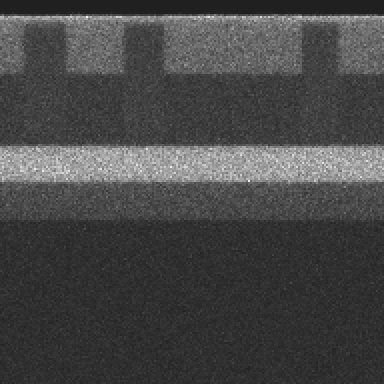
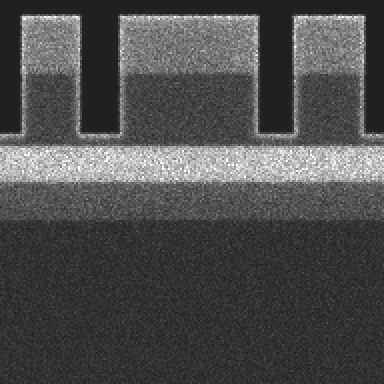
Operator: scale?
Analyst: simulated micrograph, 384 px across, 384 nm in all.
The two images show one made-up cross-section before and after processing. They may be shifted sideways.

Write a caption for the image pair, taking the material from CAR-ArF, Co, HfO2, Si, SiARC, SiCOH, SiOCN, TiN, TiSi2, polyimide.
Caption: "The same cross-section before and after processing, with SiARC removed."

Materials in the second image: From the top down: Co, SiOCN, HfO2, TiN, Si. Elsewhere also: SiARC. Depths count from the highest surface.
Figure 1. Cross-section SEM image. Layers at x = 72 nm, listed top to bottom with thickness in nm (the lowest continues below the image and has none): Co 58, SiOCN 72, HfO2 36, TiN 38, Si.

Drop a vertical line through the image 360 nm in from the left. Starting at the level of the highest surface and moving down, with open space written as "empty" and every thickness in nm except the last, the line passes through Co 58, SiOCN 72, HfO2 36, TiN 38, Si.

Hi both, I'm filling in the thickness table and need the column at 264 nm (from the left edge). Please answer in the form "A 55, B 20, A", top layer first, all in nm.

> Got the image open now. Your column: empty 118, SiOCN 12, HfO2 36, TiN 38, Si